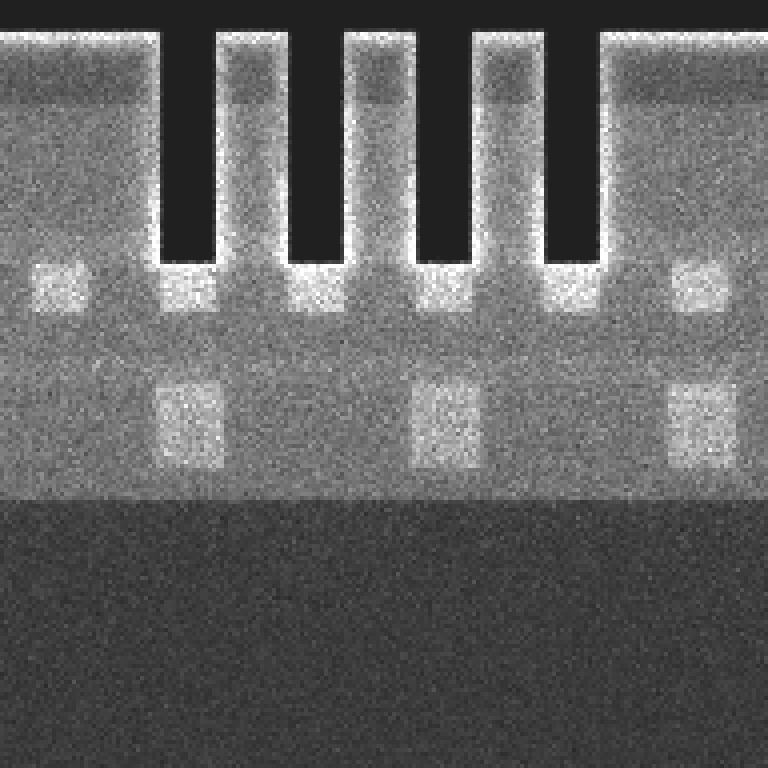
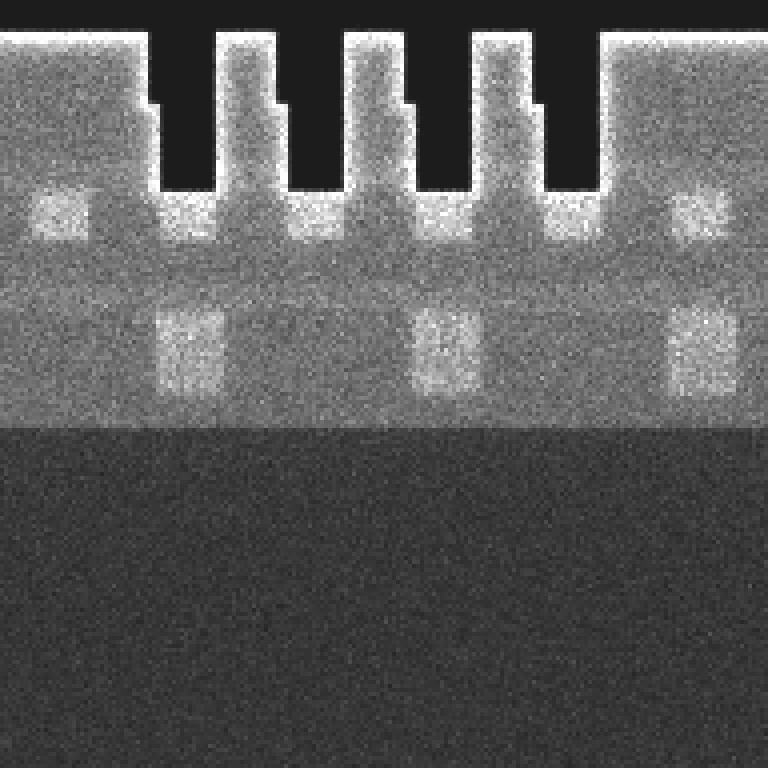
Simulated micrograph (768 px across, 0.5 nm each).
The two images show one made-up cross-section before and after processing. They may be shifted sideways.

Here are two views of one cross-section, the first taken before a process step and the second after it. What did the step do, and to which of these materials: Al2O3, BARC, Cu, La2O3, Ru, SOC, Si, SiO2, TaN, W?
It removed SOC.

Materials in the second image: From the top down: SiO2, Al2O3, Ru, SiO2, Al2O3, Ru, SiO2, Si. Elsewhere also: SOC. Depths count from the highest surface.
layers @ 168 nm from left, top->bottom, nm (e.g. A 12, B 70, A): empty 80, Ru 24, SiO2 22, Al2O3 14, SiO2 58, Si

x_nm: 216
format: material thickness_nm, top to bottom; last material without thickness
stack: empty 80, Ru 24, SiO2 22, Al2O3 14, Ru 42, SiO2 16, Si